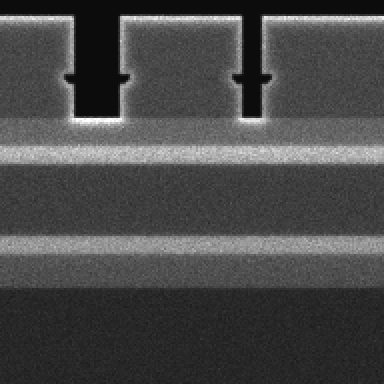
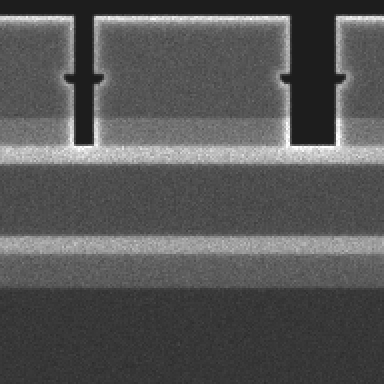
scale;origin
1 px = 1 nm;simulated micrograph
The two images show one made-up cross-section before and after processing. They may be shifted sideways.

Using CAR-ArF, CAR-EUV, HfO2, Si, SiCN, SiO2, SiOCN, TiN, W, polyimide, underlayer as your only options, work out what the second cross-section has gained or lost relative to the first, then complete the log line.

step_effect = removed SiO2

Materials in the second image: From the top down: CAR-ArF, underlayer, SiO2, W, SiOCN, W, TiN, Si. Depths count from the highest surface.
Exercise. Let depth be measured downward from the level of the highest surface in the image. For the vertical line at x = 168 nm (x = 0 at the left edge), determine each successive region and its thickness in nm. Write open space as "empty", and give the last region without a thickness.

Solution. CAR-ArF 58, underlayer 44, SiO2 28, W 18, SiOCN 72, W 18, TiN 34, Si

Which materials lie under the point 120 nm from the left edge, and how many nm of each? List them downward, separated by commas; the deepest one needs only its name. CAR-ArF 58, underlayer 44, SiO2 28, W 18, SiOCN 72, W 18, TiN 34, Si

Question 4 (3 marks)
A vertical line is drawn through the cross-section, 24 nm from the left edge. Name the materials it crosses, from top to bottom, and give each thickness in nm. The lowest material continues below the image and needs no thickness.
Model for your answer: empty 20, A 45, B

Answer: CAR-ArF 58, underlayer 44, SiO2 28, W 18, SiOCN 72, W 18, TiN 34, Si